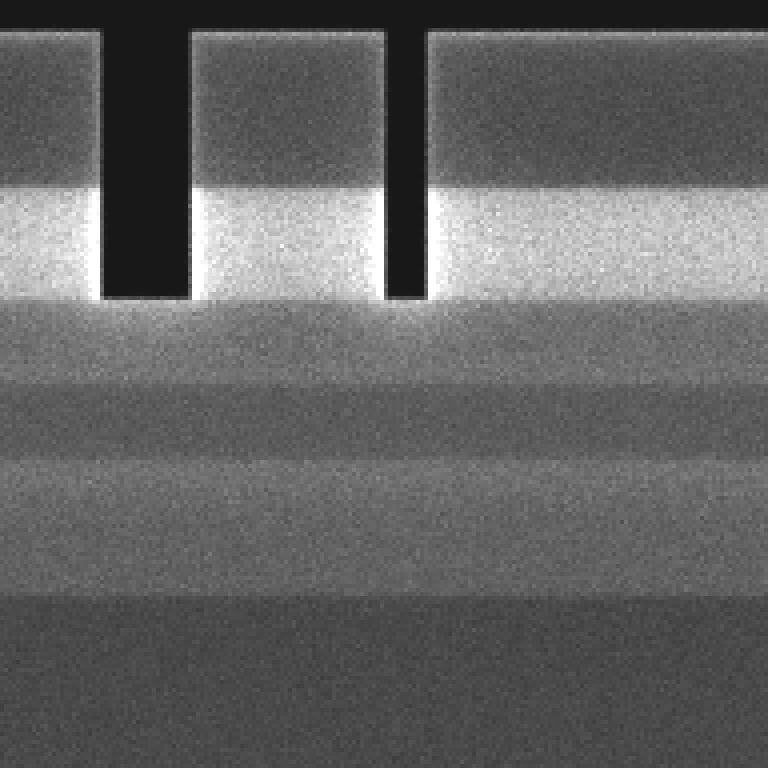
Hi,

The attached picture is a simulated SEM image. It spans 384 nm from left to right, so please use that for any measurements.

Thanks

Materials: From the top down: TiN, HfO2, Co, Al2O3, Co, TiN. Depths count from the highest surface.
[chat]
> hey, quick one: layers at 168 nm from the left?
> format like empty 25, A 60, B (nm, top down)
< TiN 78, HfO2 56, Co 42, Al2O3 38, Co 68, TiN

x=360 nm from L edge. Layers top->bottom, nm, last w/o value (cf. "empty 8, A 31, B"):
TiN 78, HfO2 56, Co 42, Al2O3 38, Co 68, TiN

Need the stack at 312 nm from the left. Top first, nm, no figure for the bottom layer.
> TiN 78, HfO2 56, Co 42, Al2O3 38, Co 68, TiN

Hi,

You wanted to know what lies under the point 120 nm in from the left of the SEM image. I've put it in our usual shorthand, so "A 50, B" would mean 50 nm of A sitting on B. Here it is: TiN 78, HfO2 56, Co 42, Al2O3 38, Co 68, TiN